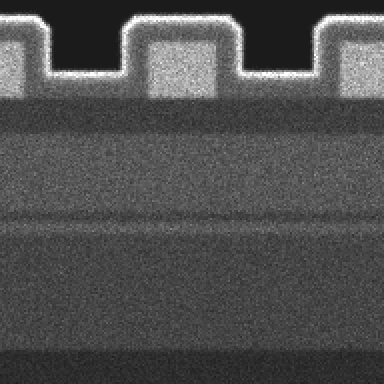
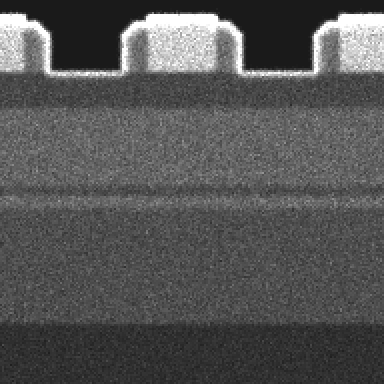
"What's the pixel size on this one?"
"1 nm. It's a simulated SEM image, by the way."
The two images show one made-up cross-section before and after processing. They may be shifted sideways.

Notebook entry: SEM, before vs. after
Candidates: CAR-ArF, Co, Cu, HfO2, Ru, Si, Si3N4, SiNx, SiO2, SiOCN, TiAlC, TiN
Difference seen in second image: SiO2 removed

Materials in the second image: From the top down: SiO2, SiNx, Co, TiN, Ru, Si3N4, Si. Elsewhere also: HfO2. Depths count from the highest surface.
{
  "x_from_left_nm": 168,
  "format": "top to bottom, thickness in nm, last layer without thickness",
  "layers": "HfO2 56, SiNx 36, Co 78, TiN 10, Ru 12, Si3N4 116, Si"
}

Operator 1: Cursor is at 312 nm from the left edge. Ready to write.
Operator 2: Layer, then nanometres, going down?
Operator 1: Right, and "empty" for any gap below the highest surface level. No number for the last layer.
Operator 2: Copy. empty 56, SiNx 36, Co 78, TiN 10, Ru 12, Si3N4 116, Si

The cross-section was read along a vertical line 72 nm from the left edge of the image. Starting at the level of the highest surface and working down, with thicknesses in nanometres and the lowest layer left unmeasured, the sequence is empty 56, SiNx 36, Co 78, TiN 10, Ru 12, Si3N4 116, Si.